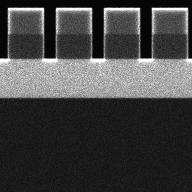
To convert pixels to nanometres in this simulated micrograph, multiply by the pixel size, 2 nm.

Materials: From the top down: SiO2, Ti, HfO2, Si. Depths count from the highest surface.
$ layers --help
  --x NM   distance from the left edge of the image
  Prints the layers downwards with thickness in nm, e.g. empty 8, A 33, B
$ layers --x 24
SiO2 52, Ti 50, HfO2 78, Si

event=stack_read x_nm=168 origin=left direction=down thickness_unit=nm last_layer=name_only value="SiO2 52, Ti 50, HfO2 78, Si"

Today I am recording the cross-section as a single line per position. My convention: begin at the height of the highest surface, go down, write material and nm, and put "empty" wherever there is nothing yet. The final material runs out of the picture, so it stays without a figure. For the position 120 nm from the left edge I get SiO2 52, Ti 50, HfO2 78, Si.